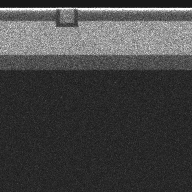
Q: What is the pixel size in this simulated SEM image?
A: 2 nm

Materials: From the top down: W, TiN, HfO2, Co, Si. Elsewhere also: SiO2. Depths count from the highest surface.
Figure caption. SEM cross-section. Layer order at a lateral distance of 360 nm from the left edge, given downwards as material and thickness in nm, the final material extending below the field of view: SiO2 26, HfO2 68, Co 30, Si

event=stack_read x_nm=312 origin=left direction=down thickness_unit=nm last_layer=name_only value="SiO2 26, HfO2 68, Co 30, Si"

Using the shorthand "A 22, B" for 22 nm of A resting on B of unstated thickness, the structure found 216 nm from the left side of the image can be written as SiO2 26, HfO2 68, Co 30, Si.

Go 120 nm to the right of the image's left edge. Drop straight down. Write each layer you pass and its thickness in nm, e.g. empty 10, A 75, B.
W 30, TiN 8, HfO2 56, Co 30, Si